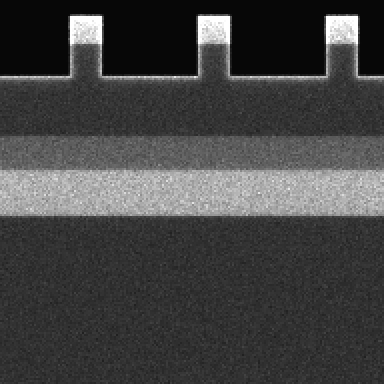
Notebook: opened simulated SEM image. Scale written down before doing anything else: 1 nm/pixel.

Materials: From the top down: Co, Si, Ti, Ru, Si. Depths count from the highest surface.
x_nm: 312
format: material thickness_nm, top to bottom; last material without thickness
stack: empty 60, Si 60, Ti 34, Ru 46, Si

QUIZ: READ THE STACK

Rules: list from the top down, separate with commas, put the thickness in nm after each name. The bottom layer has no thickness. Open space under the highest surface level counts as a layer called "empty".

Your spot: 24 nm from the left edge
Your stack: empty 60, Si 60, Ti 34, Ru 46, Si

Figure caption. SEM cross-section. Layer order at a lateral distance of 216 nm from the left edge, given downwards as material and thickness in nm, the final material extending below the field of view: Co 28, Si 92, Ti 34, Ru 46, Si